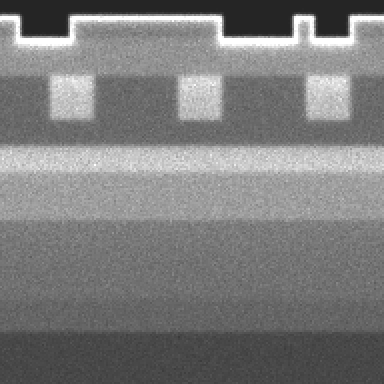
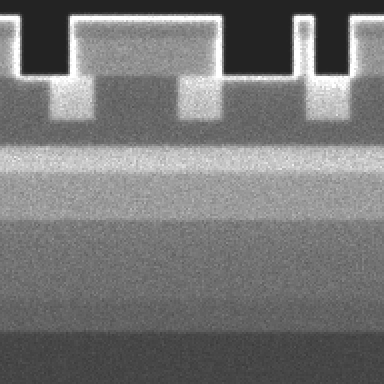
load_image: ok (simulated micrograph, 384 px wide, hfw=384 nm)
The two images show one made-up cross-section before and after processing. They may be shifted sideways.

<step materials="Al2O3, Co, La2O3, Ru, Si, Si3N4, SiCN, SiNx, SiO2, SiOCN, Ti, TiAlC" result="removed SiO2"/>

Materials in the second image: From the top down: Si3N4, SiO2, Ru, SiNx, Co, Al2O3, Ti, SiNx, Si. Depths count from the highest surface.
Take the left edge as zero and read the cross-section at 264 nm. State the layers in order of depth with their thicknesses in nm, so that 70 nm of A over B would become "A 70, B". empty 60, SiNx 70, Co 26, Al2O3 48, Ti 80, SiNx 32, Si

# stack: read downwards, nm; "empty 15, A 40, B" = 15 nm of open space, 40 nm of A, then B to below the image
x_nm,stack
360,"Si3N4 22, SiO2 38, SiNx 70, Co 26, Al2O3 48, Ti 80, SiNx 32, Si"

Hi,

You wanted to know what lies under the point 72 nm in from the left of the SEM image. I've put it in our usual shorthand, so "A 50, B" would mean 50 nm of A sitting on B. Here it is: Si3N4 22, SiO2 38, Ru 44, SiNx 26, Co 26, Al2O3 48, Ti 80, SiNx 32, Si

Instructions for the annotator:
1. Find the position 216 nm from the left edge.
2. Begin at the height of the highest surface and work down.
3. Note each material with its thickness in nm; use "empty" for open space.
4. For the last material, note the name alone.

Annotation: Si3N4 22, SiO2 38, Ru 44, SiNx 26, Co 26, Al2O3 48, Ti 80, SiNx 32, Si